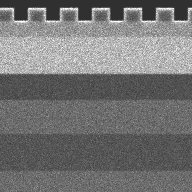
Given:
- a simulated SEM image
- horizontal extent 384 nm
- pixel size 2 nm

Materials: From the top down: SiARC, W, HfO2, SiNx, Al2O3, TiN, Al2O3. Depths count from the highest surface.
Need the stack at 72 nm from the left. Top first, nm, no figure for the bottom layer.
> SiARC 26, W 32, HfO2 74, SiNx 52, Al2O3 68, TiN 74, Al2O3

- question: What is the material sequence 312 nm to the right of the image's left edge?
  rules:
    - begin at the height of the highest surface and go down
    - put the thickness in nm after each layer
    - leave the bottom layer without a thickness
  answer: SiARC 26, W 32, HfO2 74, SiNx 52, Al2O3 68, TiN 74, Al2O3